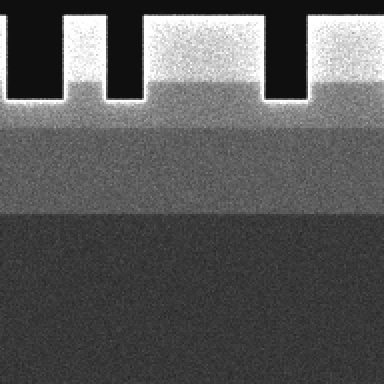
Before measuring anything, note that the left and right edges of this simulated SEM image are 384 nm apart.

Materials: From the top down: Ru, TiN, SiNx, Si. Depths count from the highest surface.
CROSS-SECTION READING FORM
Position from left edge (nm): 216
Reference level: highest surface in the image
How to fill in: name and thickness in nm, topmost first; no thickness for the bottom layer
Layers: Ru 66, TiN 46, SiNx 86, Si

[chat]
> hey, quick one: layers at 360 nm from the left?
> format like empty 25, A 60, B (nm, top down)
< Ru 66, TiN 46, SiNx 86, Si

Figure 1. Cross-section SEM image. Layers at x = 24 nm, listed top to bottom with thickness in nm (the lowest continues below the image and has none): empty 84, TiN 28, SiNx 86, Si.